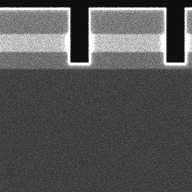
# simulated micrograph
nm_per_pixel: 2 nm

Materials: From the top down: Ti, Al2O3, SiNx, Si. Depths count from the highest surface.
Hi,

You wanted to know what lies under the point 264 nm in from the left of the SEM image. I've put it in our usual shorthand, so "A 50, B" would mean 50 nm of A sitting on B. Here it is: Ti 52, Al2O3 36, SiNx 34, Si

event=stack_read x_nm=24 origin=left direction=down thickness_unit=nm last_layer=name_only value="Ti 52, Al2O3 36, SiNx 34, Si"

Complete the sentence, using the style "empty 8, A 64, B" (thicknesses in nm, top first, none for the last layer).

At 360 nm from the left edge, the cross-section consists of empty 110, SiNx 12, Si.